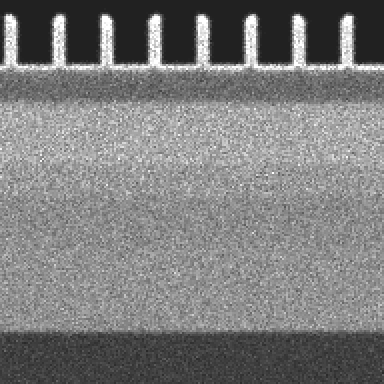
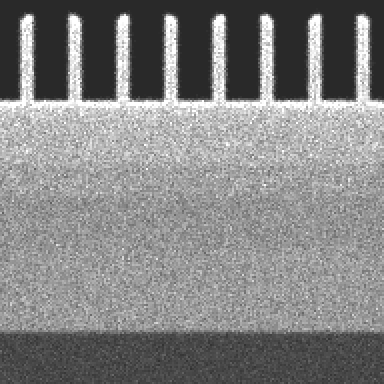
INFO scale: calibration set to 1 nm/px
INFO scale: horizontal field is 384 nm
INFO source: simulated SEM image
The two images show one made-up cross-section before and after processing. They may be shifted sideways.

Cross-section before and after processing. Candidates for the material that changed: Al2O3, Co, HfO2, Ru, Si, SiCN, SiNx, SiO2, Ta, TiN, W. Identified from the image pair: TiN (removed).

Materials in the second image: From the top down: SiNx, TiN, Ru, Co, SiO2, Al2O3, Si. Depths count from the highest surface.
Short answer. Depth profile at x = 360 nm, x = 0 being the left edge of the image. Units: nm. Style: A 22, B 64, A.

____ SiNx 50, TiN 36, Ru 62, Co 32, SiO2 52, Al2O3 84, Si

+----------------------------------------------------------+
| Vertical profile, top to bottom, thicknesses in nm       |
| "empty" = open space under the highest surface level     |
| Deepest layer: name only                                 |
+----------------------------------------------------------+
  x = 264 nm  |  SiNx 50, TiN 36, Ru 62, Co 32, SiO2 52, Al2O3 84, Si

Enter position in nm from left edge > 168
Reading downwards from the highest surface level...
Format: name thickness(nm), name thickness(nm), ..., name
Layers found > SiNx 50, TiN 36, Ru 62, Co 32, SiO2 52, Al2O3 84, Si